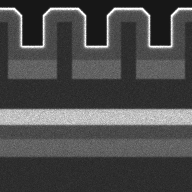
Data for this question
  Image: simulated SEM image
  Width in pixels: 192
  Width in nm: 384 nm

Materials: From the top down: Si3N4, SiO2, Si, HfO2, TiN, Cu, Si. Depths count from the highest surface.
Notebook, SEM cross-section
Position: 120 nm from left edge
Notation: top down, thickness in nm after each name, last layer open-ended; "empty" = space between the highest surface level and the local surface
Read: Si3N4 28, Si 174, HfO2 32, TiN 28, Cu 36, Si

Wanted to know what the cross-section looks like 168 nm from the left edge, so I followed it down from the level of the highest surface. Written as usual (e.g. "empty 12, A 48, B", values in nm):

empty 12, Si3N4 92, SiO2 38, Si 60, HfO2 32, TiN 28, Cu 36, Si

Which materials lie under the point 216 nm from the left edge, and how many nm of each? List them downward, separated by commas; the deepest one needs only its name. empty 12, Si3N4 92, SiO2 38, Si 60, HfO2 32, TiN 28, Cu 36, Si